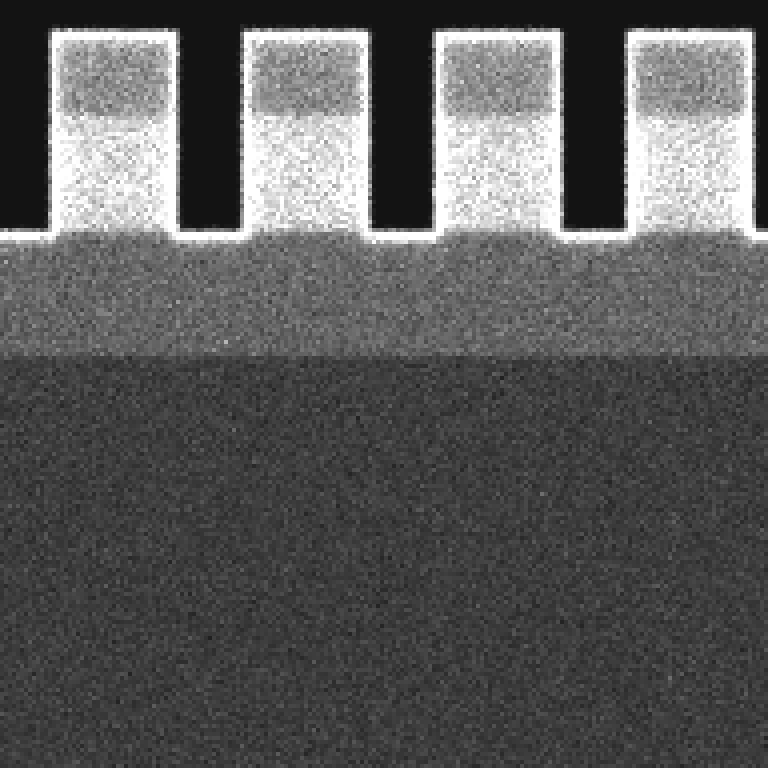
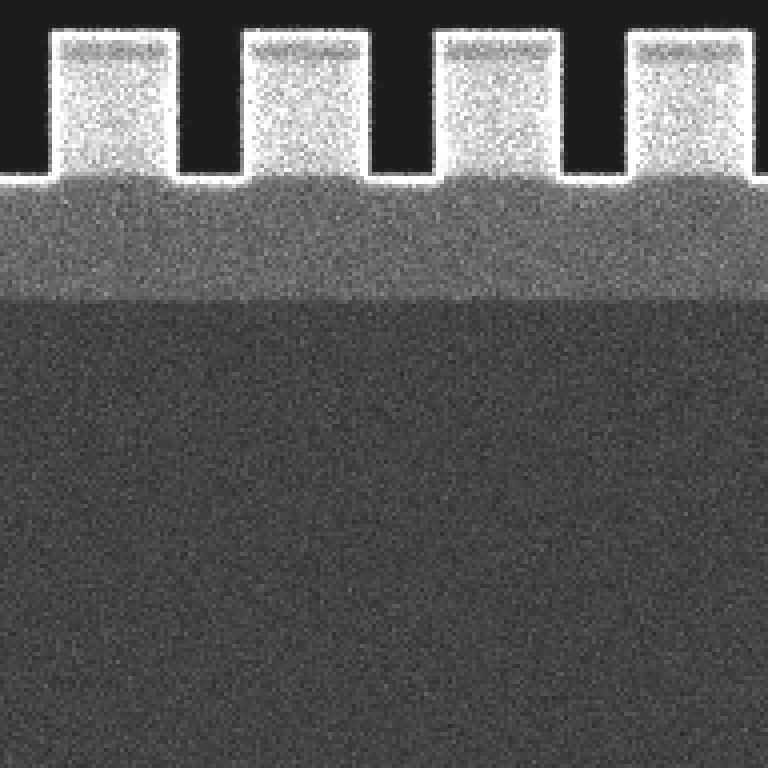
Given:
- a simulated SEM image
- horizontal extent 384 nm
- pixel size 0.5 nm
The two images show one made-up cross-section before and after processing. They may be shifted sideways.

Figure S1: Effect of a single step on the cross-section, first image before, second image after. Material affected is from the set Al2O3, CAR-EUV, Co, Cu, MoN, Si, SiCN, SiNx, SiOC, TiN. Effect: removed TiN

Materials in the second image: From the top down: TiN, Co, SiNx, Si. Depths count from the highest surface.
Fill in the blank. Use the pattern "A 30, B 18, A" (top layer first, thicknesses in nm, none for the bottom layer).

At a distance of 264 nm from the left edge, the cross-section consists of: TiN 14, Co 58, SiNx 62, Si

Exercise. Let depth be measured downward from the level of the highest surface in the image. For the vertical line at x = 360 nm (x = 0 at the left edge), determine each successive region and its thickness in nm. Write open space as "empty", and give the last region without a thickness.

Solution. TiN 14, Co 58, SiNx 62, Si